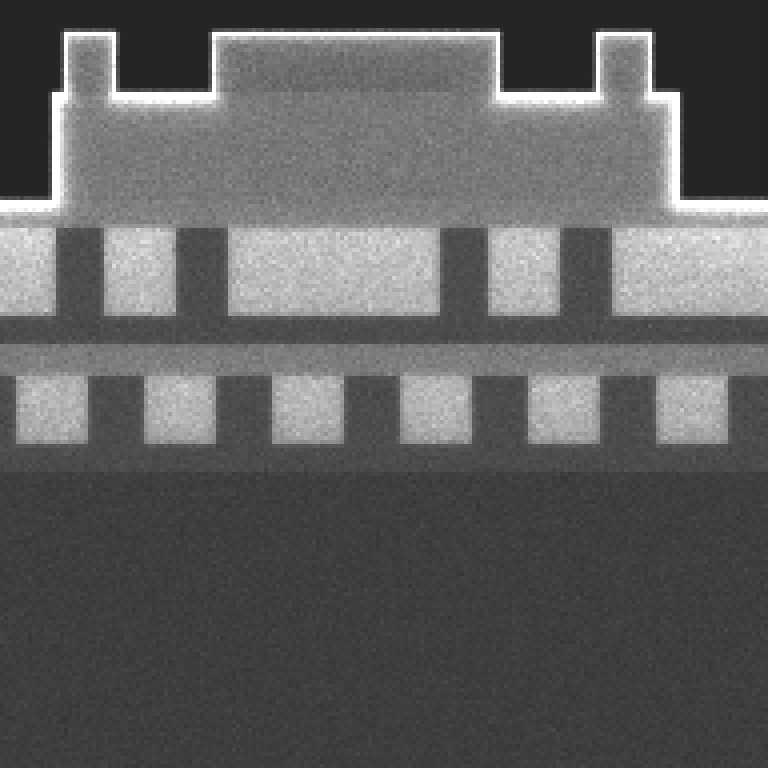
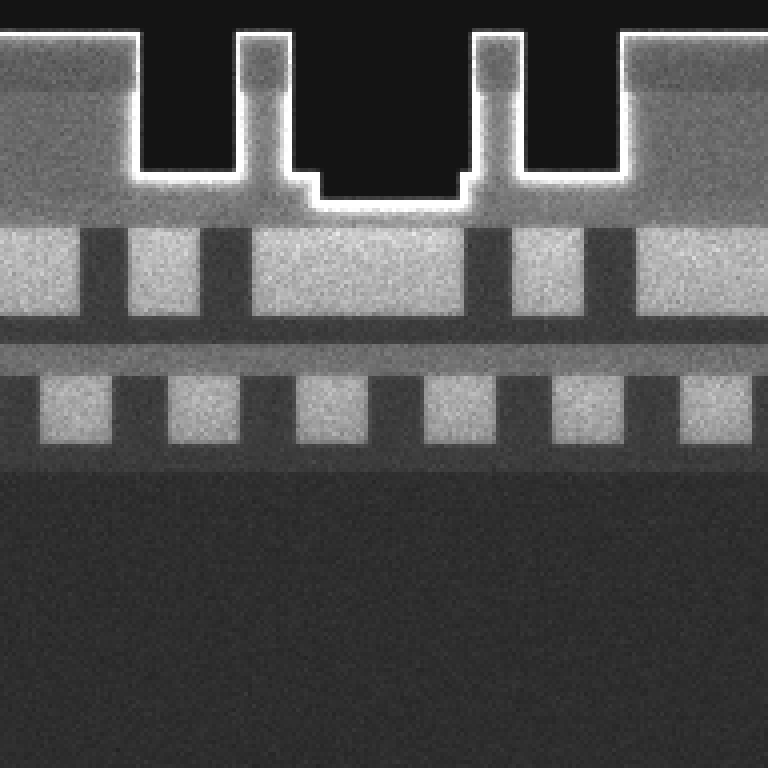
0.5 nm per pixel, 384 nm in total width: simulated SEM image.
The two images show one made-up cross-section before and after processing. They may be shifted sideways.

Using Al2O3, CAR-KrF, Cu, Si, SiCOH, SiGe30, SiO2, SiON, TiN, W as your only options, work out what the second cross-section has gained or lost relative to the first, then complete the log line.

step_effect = removed SiO2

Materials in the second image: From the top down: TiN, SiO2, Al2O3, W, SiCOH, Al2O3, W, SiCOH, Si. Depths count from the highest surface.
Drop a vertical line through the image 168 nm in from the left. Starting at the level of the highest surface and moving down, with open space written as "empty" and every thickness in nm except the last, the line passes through empty 84, Al2O3 14, W 44, SiCOH 14, Al2O3 16, W 34, SiCOH 14, Si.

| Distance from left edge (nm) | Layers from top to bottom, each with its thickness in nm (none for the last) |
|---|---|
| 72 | empty 70, SiO2 14, Al2O3 14, W 44, SiCOH 14, Al2O3 16, SiCOH 48, Si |